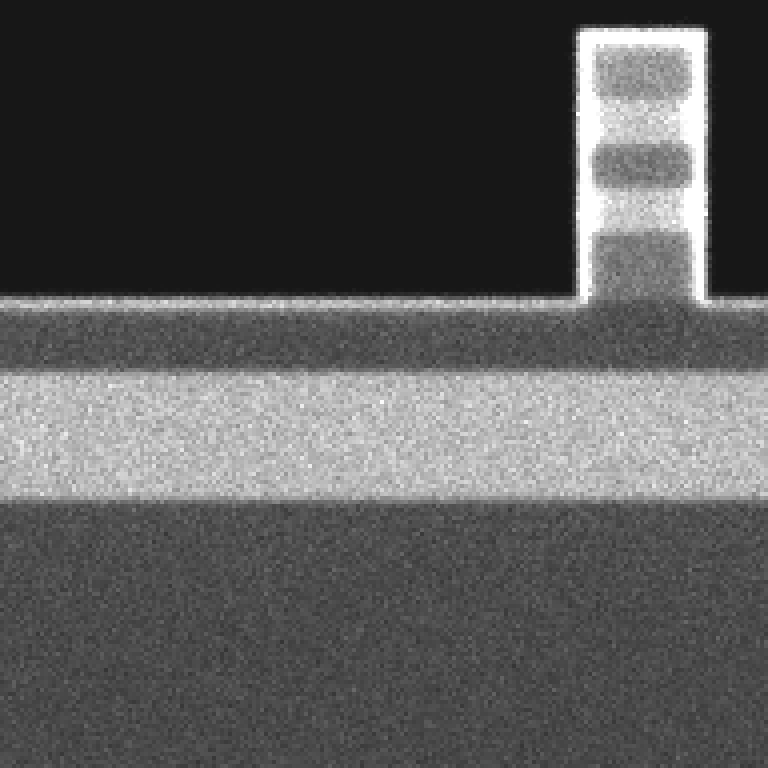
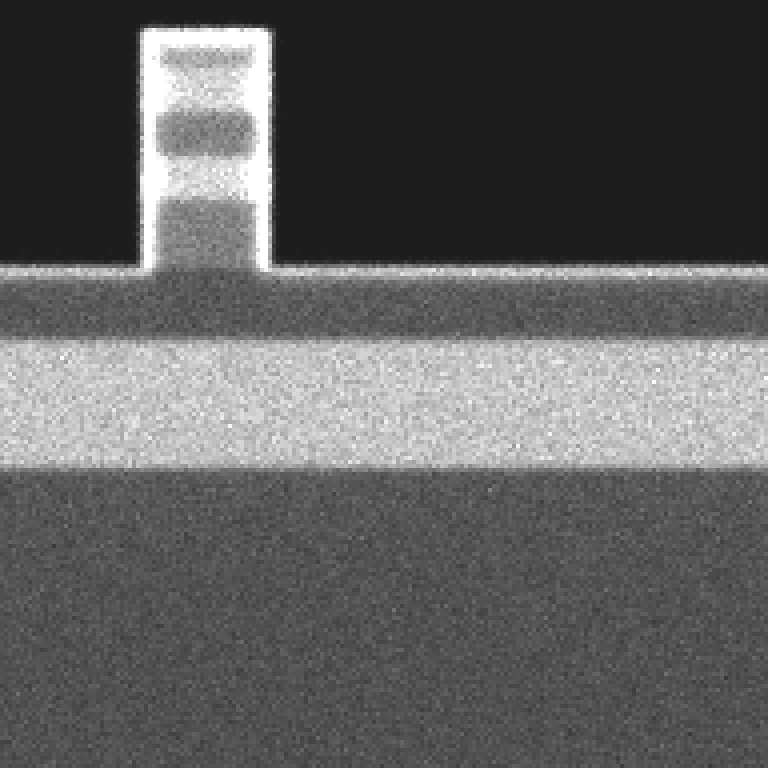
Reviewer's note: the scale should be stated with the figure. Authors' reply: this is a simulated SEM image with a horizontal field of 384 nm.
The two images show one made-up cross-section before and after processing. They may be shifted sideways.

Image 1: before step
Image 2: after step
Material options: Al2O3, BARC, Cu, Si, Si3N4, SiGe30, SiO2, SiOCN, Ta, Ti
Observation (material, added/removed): Si3N4, removed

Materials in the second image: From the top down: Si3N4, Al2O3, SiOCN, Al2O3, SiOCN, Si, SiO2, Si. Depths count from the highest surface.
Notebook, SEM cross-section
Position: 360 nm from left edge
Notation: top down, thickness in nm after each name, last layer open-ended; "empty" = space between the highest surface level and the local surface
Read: empty 118, Si 36, SiO2 64, Si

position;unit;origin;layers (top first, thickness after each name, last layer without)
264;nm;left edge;empty 118, Si 36, SiO2 64, Si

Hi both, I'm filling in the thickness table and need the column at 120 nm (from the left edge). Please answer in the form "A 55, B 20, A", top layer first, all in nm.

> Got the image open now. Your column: Si3N4 18, Al2O3 22, SiOCN 22, Al2O3 22, SiOCN 34, Si 36, SiO2 64, Si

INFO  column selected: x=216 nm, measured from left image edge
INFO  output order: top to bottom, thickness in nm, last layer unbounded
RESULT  empty 118, Si 36, SiO2 64, Si